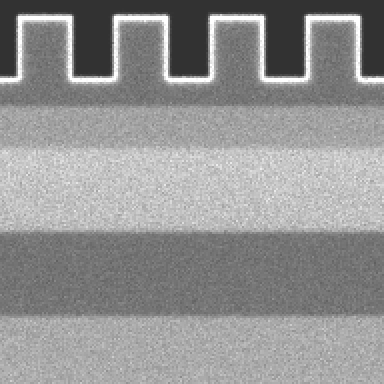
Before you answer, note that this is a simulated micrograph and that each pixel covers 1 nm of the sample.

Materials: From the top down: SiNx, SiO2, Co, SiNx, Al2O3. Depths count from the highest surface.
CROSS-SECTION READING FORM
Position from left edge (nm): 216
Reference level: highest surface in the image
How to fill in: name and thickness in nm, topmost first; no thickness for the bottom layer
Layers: SiNx 90, SiO2 42, Co 84, SiNx 84, Al2O3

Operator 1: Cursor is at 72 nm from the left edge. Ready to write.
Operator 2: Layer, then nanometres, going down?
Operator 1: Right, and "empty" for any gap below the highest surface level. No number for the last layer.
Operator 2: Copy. empty 62, SiNx 28, SiO2 42, Co 84, SiNx 84, Al2O3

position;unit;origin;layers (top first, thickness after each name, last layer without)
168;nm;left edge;empty 62, SiNx 28, SiO2 42, Co 84, SiNx 84, Al2O3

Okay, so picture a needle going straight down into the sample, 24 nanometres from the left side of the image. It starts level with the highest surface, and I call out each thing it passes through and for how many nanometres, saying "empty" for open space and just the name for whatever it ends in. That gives SiNx 90, SiO2 42, Co 84, SiNx 84, Al2O3